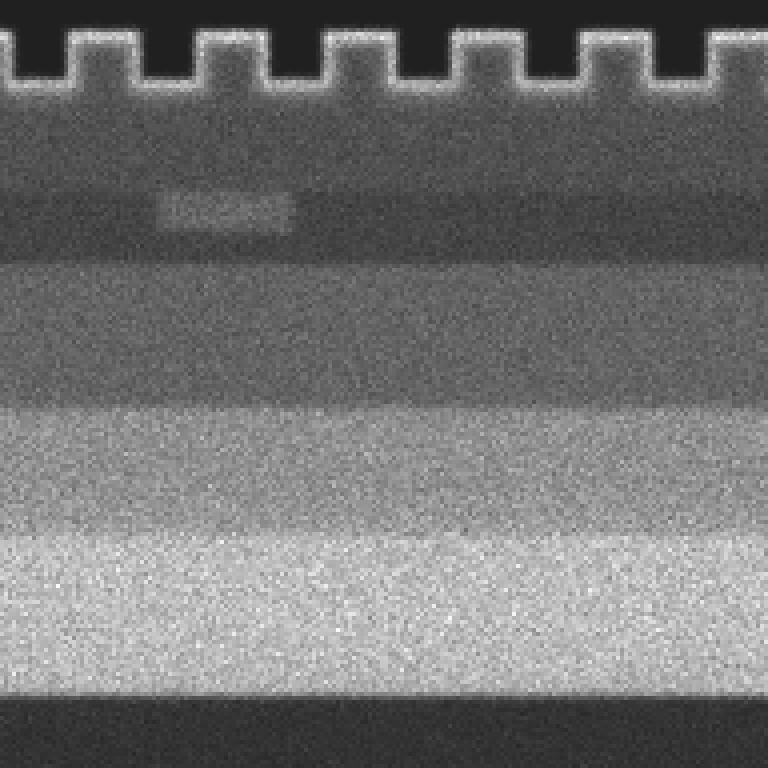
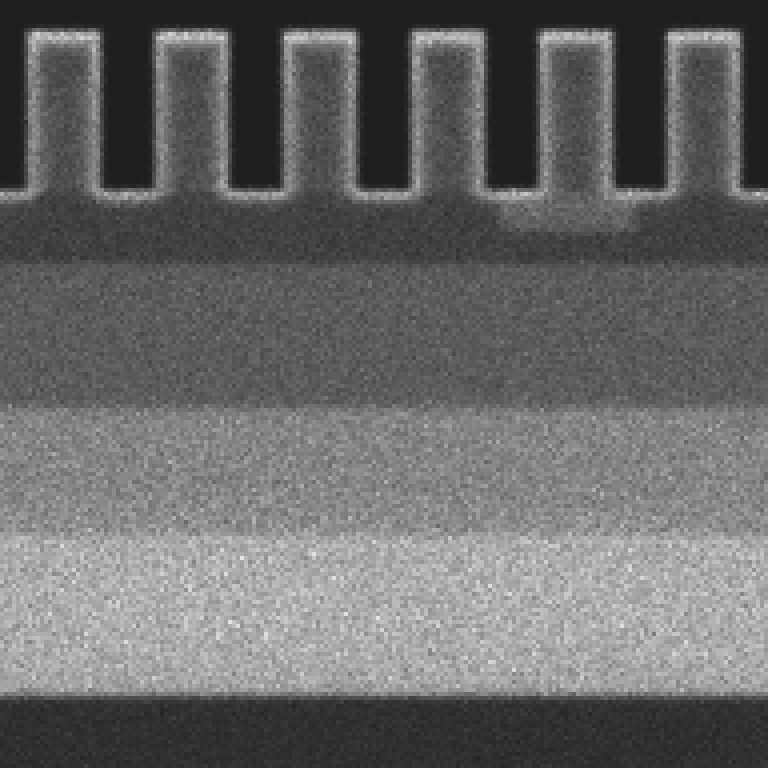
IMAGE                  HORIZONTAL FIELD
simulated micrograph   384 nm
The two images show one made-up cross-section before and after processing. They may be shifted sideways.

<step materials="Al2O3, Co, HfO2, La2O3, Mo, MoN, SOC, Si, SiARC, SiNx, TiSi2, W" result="removed SOC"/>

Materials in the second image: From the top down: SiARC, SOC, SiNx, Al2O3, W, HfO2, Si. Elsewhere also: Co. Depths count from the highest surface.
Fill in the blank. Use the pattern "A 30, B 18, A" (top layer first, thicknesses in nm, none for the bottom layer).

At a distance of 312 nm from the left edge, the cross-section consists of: empty 80, Co 20, SiNx 16, Al2O3 72, W 64, HfO2 80, Si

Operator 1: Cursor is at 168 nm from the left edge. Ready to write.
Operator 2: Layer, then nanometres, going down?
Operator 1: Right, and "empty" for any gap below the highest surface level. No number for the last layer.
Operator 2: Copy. SiARC 24, SOC 56, SiNx 36, Al2O3 72, W 64, HfO2 80, Si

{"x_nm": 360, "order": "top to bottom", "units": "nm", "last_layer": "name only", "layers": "SiARC 24, SOC 56, SiNx 36, Al2O3 72, W 64, HfO2 80, Si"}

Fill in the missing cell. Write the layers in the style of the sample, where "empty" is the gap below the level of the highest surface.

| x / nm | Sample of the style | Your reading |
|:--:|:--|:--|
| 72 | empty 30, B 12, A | empty 80, SiNx 36, Al2O3 72, W 64, HfO2 80, Si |